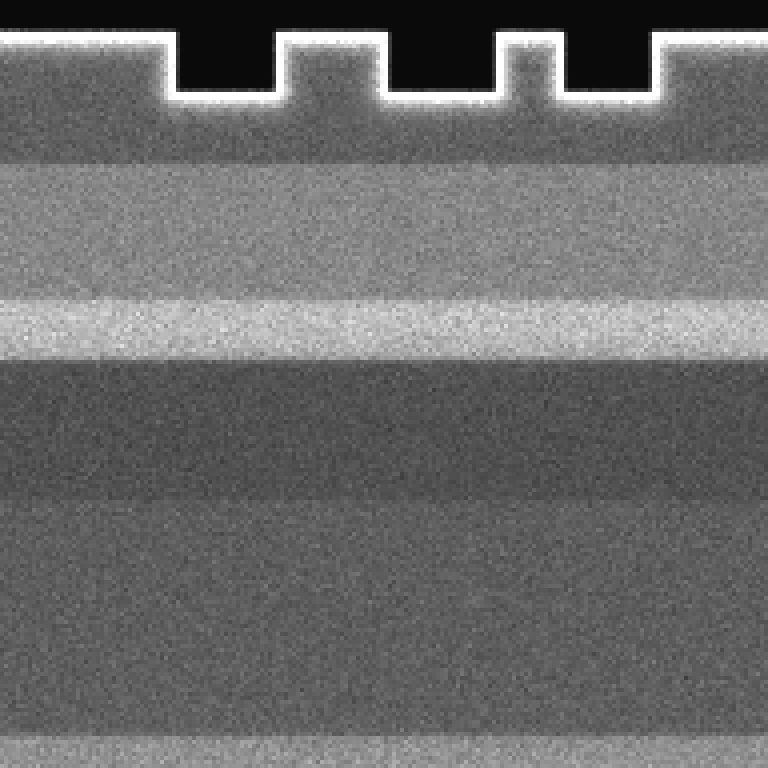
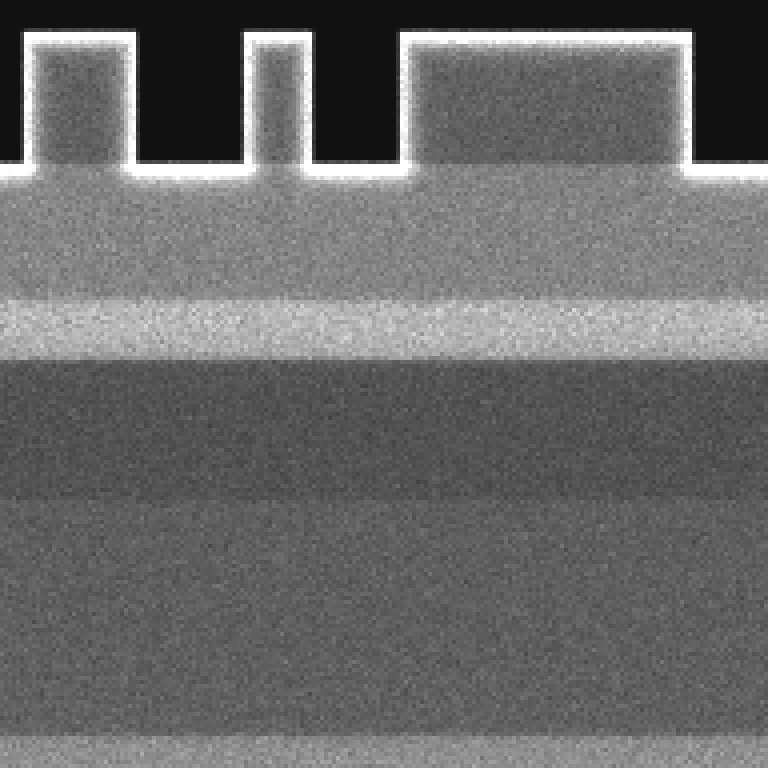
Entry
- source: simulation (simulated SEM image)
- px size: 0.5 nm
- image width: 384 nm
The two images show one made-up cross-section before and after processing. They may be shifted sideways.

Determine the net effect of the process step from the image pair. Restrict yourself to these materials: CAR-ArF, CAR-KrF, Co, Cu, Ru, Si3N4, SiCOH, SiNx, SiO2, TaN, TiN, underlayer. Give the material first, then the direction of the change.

underlayer: removed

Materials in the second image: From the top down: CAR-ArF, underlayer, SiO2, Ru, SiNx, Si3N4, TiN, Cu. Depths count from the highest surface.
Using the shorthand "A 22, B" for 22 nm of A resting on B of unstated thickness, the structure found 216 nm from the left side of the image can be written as CAR-ArF 30, underlayer 36, SiO2 68, Ru 30, SiNx 70, Si3N4 76, TiN 42, Cu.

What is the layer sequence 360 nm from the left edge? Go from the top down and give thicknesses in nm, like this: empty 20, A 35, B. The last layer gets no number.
empty 66, SiO2 68, Ru 30, SiNx 70, Si3N4 76, TiN 42, Cu